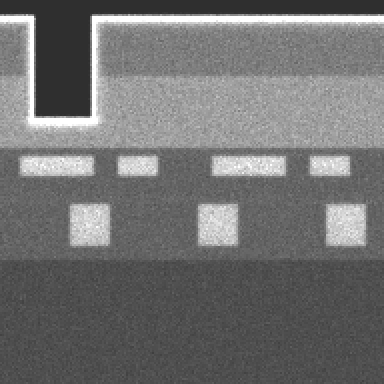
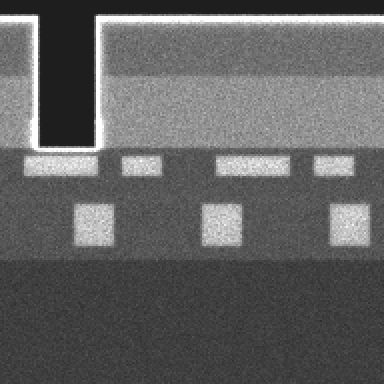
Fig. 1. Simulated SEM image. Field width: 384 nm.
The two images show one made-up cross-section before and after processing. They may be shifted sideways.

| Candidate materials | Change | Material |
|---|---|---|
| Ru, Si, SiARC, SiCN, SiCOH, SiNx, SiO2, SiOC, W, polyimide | removed | SiO2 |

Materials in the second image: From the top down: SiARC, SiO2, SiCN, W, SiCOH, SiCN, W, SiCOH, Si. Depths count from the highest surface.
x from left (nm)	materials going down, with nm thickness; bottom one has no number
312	SiARC 60, SiO2 72, SiCN 8, SiCOH 40, SiCN 8, SiCOH 56, Si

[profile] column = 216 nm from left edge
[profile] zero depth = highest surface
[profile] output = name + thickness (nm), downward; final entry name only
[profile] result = SiARC 60, SiO2 72, SiCN 8, W 20, SiCOH 20, SiCN 8, W 42, SiCOH 14, Si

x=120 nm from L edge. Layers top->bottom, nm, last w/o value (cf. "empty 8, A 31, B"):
SiARC 60, SiO2 72, SiCN 8, SiCOH 40, SiCN 8, SiCOH 56, Si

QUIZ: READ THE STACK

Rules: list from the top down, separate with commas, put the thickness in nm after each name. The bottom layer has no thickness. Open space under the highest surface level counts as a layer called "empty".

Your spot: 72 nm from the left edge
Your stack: empty 132, SiCN 8, W 20, SiCOH 20, SiCN 8, SiCOH 56, Si